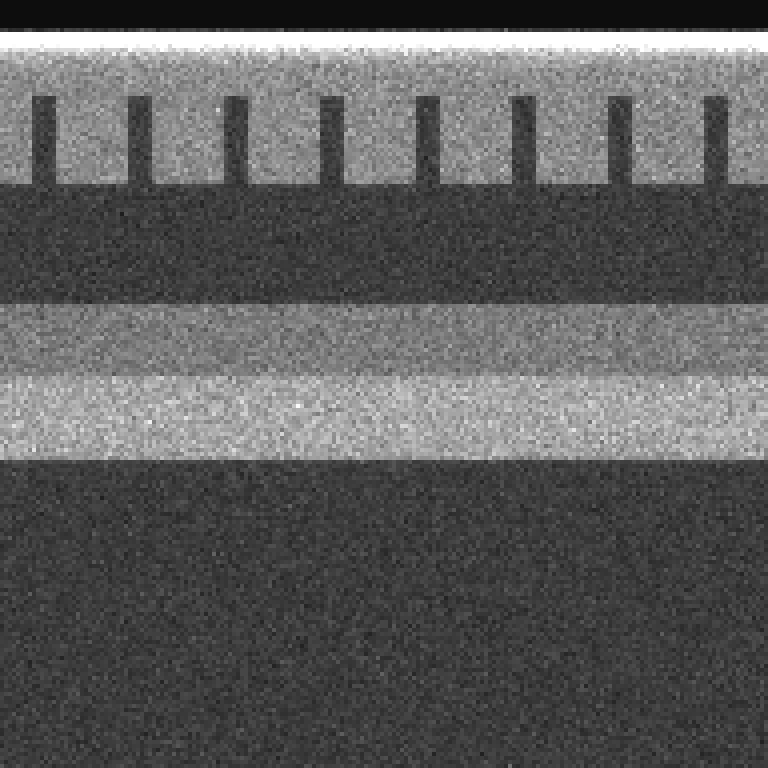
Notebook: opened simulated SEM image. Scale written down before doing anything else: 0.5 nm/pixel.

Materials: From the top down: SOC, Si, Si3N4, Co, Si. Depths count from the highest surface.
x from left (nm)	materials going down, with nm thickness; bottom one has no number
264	SOC 32, Si 104, Si3N4 36, Co 42, Si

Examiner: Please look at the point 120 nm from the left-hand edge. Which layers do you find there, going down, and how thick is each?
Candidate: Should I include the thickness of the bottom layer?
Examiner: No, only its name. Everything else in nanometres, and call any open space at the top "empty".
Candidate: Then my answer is SOC 32, Si 104, Si3N4 36, Co 42, Si